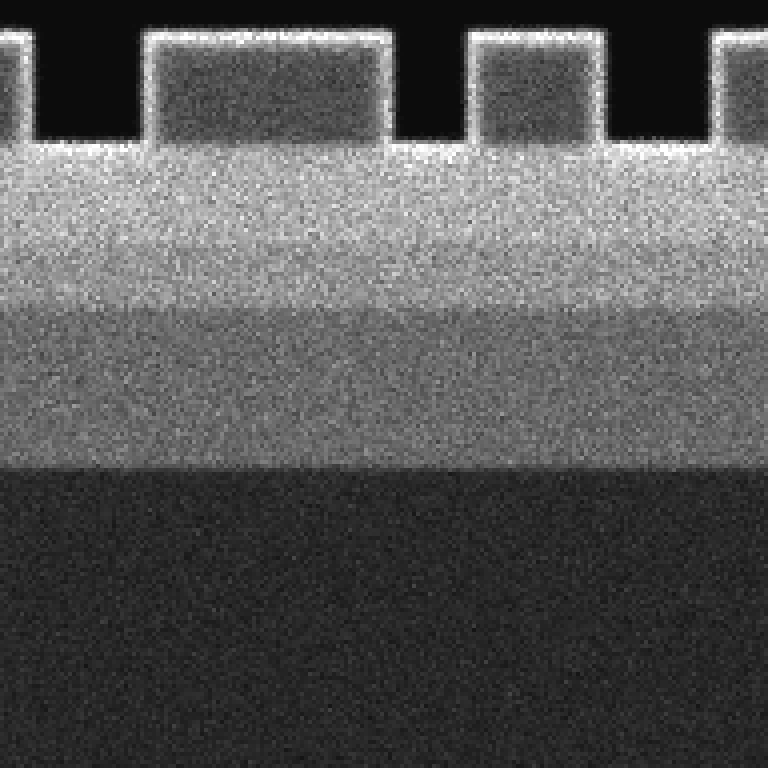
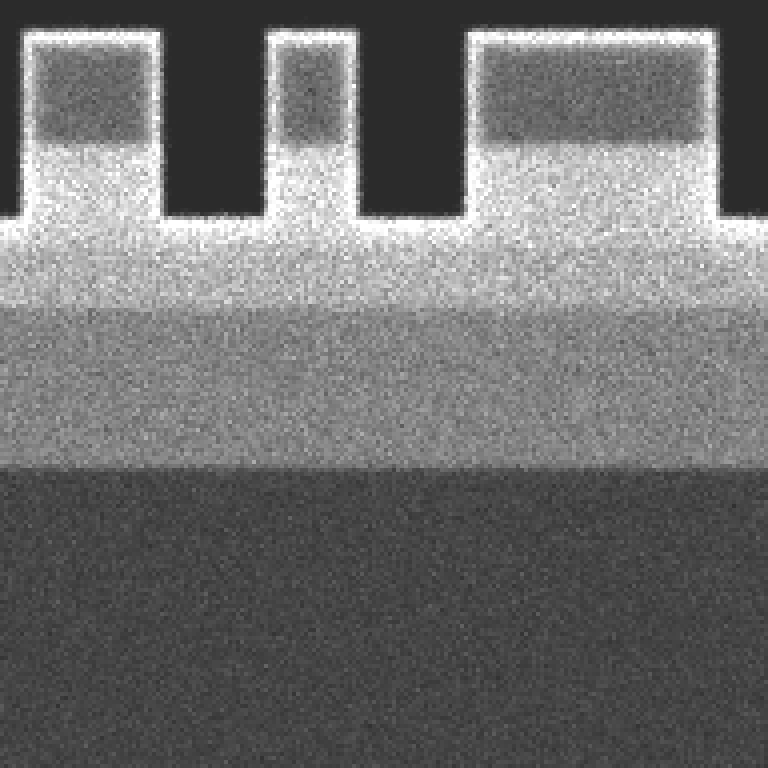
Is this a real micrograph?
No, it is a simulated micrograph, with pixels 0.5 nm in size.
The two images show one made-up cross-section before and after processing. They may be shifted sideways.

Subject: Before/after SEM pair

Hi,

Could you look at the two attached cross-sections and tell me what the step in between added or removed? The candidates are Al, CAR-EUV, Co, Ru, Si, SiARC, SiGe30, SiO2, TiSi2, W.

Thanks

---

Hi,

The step removed W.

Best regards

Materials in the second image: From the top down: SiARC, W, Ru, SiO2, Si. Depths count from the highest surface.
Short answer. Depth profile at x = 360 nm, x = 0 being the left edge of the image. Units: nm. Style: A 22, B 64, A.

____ empty 94, W 12, Ru 32, SiO2 80, Si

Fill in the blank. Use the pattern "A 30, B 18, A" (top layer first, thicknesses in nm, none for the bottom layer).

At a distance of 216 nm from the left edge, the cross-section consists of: empty 94, W 12, Ru 32, SiO2 80, Si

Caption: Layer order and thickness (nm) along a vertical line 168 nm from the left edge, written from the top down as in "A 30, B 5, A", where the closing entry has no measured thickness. SiARC 56, W 50, Ru 32, SiO2 80, Si